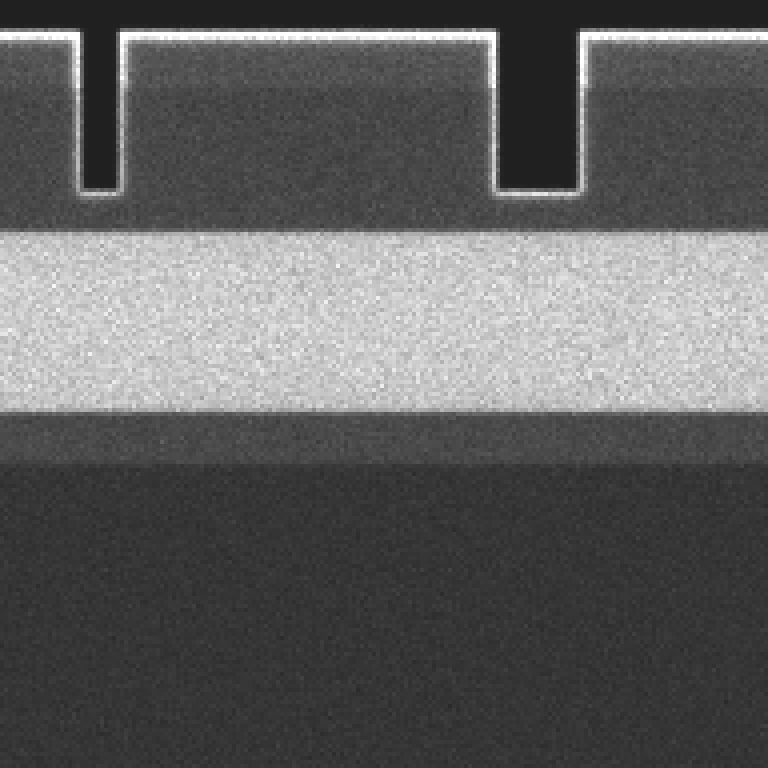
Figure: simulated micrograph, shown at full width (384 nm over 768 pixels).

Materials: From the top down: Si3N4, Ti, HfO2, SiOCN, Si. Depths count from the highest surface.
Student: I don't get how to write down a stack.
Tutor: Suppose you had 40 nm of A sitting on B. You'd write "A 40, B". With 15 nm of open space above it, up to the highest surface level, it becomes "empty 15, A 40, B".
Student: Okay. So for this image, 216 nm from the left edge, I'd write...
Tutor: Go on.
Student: Si3N4 28, Ti 72, HfO2 90, SiOCN 26, Si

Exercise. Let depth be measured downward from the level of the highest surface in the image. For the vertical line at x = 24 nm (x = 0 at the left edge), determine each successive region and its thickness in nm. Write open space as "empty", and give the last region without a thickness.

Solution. Si3N4 28, Ti 72, HfO2 90, SiOCN 26, Si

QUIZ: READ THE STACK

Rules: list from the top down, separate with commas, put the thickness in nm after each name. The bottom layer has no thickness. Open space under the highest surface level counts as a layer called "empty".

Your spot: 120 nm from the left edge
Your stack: Si3N4 28, Ti 72, HfO2 90, SiOCN 26, Si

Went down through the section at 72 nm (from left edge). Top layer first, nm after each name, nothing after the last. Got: Si3N4 28, Ti 72, HfO2 90, SiOCN 26, Si